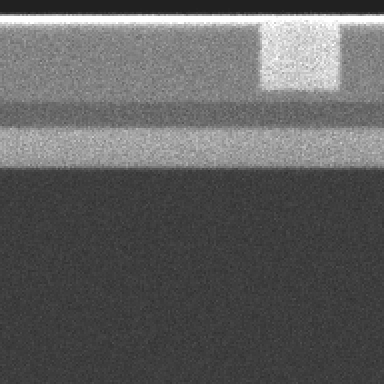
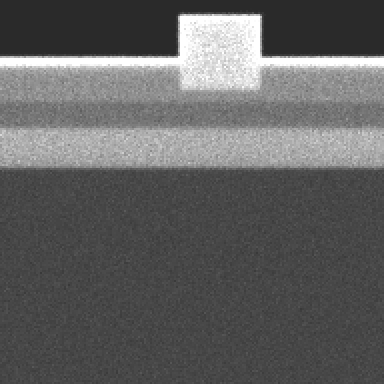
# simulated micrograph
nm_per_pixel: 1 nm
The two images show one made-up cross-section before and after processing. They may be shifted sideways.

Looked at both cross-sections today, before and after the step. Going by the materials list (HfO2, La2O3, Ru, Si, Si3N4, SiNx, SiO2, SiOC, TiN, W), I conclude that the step removed SiO2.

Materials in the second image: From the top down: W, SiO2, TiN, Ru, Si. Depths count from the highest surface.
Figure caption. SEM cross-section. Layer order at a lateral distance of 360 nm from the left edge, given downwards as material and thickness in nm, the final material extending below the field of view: empty 42, SiO2 44, TiN 26, Ru 40, Si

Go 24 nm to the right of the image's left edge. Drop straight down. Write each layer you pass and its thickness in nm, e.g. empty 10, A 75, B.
empty 42, SiO2 44, TiN 26, Ru 40, Si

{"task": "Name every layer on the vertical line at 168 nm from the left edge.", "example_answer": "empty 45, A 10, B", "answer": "empty 42, SiO2 44, TiN 26, Ru 40, Si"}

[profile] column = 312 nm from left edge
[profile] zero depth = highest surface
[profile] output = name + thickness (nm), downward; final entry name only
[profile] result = empty 42, SiO2 44, TiN 26, Ru 40, Si